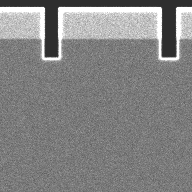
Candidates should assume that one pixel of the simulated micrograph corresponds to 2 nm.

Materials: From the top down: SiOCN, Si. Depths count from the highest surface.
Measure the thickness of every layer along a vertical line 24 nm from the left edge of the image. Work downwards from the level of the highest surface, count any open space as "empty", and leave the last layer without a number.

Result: SiOCN 62, Si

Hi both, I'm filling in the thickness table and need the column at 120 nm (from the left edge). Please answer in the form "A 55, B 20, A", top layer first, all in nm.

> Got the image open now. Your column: SiOCN 62, Si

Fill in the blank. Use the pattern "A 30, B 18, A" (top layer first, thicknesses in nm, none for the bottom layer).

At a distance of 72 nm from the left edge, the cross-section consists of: SiOCN 62, Si